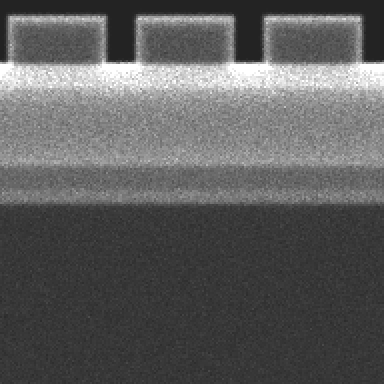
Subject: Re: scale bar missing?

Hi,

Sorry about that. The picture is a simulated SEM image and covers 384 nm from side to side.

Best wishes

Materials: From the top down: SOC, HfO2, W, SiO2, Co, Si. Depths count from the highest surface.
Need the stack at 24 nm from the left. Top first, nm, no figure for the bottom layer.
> SOC 48, HfO2 24, W 78, SiO2 24, Co 14, Si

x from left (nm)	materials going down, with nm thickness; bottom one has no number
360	SOC 48, HfO2 24, W 78, SiO2 24, Co 14, Si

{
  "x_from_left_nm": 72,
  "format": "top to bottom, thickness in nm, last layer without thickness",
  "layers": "SOC 48, HfO2 24, W 78, SiO2 24, Co 14, Si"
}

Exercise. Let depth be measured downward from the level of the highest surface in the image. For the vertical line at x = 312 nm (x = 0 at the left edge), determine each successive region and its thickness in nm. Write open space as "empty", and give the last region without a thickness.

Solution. SOC 48, HfO2 24, W 78, SiO2 24, Co 14, Si